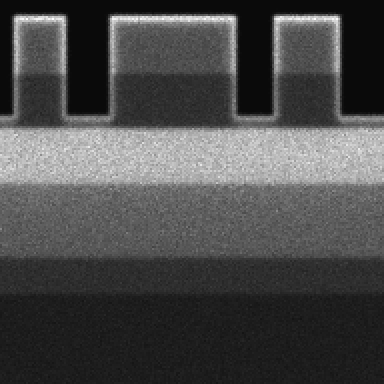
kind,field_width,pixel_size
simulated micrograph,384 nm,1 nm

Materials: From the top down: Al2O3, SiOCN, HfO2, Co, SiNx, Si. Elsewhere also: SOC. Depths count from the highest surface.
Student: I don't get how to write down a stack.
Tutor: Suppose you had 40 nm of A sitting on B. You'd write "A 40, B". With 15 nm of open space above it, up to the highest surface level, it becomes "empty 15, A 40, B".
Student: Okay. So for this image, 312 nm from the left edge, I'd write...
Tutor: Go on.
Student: Al2O3 58, SiOCN 54, HfO2 56, Co 74, SiNx 36, Si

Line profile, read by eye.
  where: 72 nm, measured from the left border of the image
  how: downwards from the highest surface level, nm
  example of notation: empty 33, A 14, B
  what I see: empty 100, SOC 12, HfO2 56, Co 74, SiNx 36, Si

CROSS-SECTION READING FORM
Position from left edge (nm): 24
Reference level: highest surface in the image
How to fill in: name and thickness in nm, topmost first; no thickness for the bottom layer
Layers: Al2O3 58, SiOCN 54, HfO2 56, Co 74, SiNx 36, Si